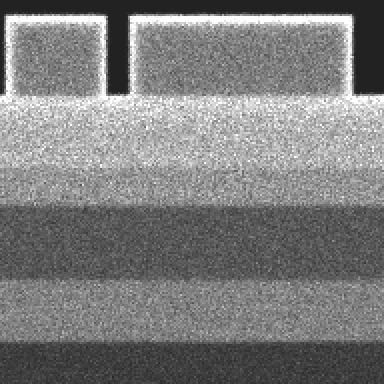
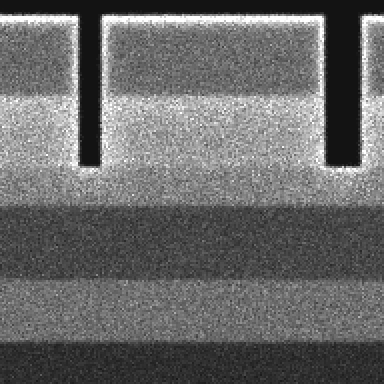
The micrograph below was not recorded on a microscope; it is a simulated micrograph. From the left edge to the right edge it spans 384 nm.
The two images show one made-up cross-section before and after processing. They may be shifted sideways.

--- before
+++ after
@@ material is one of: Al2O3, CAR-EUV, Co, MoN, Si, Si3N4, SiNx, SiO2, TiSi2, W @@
W removed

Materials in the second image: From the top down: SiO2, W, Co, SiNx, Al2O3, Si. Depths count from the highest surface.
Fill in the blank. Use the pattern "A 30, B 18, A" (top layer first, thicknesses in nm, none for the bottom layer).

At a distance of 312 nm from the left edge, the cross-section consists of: SiO2 80, W 72, Co 38, SiNx 74, Al2O3 62, Si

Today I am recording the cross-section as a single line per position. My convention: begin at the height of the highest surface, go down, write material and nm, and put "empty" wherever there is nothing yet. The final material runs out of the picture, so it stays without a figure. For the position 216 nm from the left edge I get SiO2 80, W 72, Co 38, SiNx 74, Al2O3 62, Si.